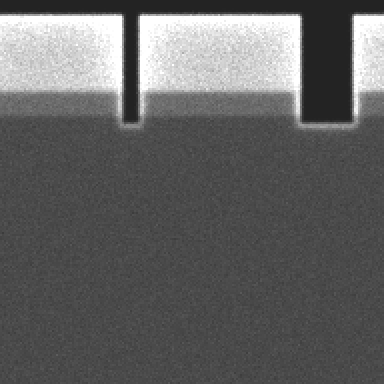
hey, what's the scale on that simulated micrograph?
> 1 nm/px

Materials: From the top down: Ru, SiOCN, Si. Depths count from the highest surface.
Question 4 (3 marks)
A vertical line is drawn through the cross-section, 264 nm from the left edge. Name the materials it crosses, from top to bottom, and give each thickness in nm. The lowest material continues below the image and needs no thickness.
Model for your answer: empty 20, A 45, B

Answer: Ru 76, SiOCN 24, Si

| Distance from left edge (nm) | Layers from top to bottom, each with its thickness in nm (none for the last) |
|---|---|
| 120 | Ru 76, SiOCN 24, Si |